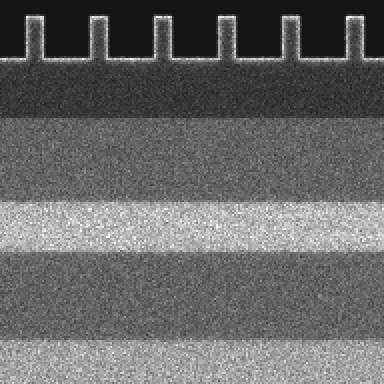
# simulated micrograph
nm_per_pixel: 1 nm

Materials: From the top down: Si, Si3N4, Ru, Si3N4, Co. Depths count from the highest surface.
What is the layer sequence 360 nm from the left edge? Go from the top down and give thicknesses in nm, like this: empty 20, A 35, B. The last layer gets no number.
Si 102, Si3N4 84, Ru 50, Si3N4 88, Co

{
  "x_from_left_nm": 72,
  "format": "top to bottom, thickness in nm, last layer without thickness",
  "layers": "empty 42, Si 60, Si3N4 84, Ru 50, Si3N4 88, Co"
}